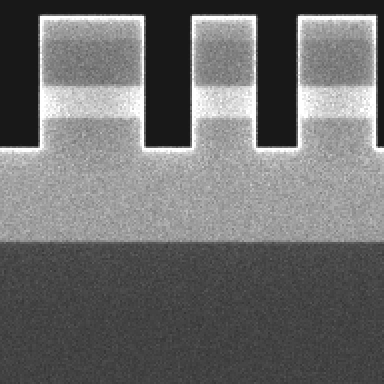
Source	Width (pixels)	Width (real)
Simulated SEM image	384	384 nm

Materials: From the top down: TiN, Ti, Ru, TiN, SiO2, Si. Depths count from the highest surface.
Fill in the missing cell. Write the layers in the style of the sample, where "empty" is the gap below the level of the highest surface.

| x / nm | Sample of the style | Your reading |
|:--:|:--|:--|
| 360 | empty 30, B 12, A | TiN 24, Ti 46, Ru 32, TiN 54, SiO2 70, Si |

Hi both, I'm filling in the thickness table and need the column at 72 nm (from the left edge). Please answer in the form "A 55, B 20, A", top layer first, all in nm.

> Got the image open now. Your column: TiN 24, Ti 46, Ru 32, TiN 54, SiO2 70, Si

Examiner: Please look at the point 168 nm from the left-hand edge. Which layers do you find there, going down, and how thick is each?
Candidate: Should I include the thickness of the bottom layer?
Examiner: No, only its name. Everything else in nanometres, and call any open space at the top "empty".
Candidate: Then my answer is empty 132, TiN 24, SiO2 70, Si